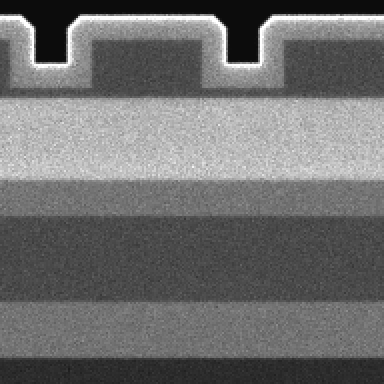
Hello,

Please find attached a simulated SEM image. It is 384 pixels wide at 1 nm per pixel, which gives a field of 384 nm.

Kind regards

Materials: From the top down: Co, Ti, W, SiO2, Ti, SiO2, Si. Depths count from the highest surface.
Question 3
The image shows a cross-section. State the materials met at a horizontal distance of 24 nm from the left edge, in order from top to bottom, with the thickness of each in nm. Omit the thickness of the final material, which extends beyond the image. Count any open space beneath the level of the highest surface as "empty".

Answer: empty 4, Co 68, Ti 10, W 82, SiO2 36, Ti 86, SiO2 56, Si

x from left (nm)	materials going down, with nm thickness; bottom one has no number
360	Co 24, Ti 58, W 82, SiO2 36, Ti 86, SiO2 56, Si